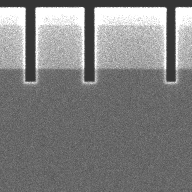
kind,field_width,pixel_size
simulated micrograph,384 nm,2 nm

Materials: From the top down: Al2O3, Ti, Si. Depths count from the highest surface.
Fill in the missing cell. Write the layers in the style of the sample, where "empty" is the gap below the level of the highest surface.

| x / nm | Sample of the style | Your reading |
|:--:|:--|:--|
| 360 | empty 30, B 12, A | Al2O3 34, Ti 88, Si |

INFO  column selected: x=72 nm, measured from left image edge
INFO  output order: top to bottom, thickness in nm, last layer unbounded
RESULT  Al2O3 34, Ti 88, Si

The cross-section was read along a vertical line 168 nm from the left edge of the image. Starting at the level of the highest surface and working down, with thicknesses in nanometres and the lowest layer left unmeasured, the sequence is empty 148, Si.